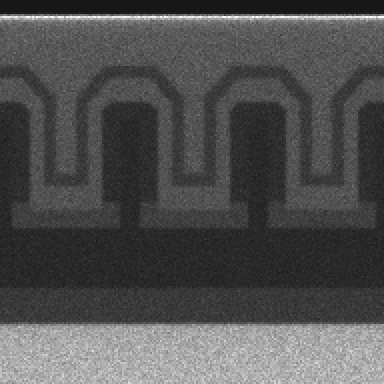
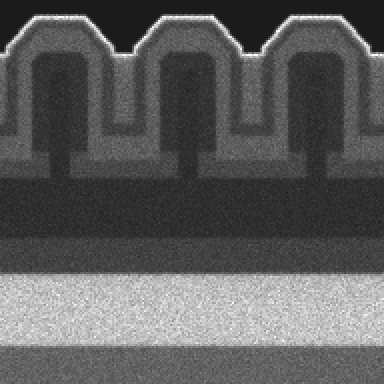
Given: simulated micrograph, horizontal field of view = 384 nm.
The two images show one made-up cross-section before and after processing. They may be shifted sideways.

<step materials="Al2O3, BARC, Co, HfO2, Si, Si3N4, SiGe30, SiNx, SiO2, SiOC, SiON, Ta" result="removed Co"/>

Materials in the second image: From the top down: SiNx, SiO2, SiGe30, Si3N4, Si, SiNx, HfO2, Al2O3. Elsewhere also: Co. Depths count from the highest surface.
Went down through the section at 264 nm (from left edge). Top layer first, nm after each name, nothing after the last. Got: empty 28, SiNx 92, SiO2 24, Si3N4 18, Si 60, SiNx 36, HfO2 72, Al2O3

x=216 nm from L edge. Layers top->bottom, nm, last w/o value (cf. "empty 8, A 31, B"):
empty 4, SiNx 20, SiO2 120, Si3N4 18, Si 60, SiNx 36, HfO2 72, Al2O3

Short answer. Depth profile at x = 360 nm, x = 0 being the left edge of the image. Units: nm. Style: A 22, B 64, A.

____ empty 22, SiNx 98, SiO2 24, Si3N4 18, Si 60, SiNx 36, HfO2 72, Al2O3